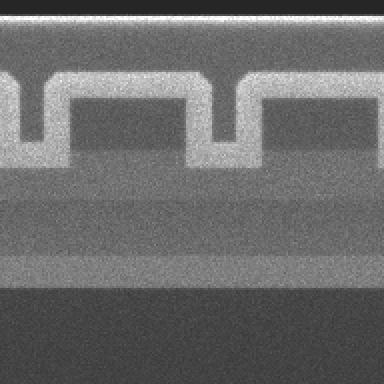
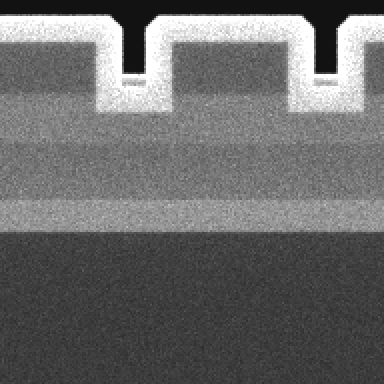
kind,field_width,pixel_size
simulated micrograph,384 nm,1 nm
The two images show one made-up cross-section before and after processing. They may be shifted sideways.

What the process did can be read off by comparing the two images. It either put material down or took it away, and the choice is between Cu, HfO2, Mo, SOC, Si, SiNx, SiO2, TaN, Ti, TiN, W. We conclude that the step removed SOC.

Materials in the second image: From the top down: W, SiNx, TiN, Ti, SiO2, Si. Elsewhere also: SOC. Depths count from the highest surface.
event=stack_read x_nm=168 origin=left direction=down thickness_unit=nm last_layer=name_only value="W 96, TiN 32, Ti 56, SiO2 32, Si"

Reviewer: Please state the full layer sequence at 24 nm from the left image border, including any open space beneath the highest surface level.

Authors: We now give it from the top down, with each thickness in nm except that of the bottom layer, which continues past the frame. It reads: W 26, SiNx 52, TiN 50, Ti 56, SiO2 32, Si